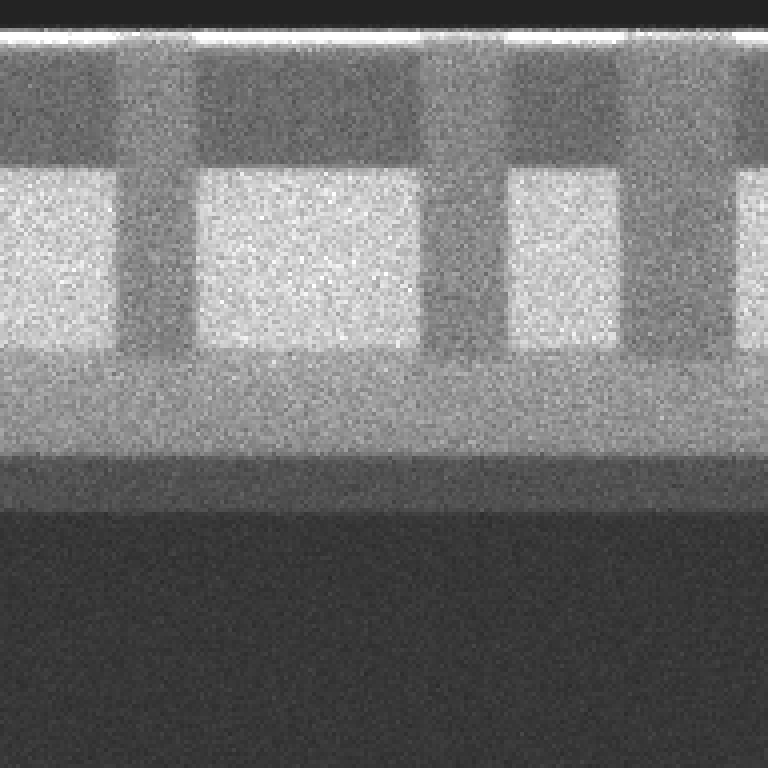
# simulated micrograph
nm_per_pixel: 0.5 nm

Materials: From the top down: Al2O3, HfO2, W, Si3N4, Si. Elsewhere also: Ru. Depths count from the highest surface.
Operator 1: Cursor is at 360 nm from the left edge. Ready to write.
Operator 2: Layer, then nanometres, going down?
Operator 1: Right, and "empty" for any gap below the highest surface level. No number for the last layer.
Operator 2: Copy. Ru 164, W 48, Si3N4 28, Si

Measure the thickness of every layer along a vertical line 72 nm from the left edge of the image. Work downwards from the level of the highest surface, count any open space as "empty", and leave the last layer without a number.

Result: Ru 164, W 48, Si3N4 28, Si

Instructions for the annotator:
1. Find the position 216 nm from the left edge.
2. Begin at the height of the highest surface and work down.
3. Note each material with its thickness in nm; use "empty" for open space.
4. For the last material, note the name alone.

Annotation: Ru 164, W 48, Si3N4 28, Si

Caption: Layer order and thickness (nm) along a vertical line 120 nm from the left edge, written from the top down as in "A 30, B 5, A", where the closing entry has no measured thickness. Al2O3 68, HfO2 90, W 54, Si3N4 28, Si